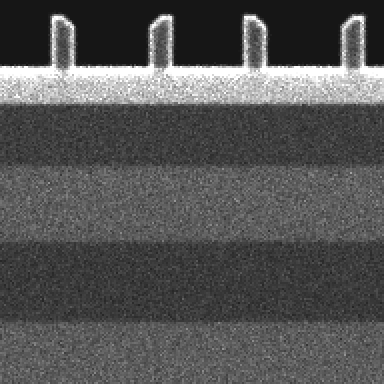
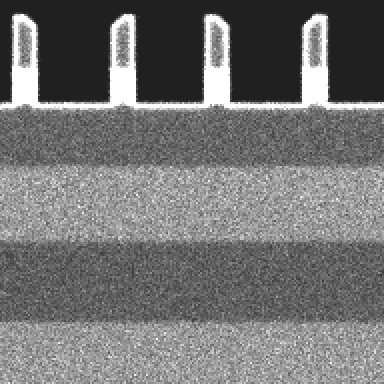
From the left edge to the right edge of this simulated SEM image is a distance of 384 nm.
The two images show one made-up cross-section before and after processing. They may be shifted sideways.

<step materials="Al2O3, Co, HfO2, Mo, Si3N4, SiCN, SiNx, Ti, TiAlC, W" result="removed HfO2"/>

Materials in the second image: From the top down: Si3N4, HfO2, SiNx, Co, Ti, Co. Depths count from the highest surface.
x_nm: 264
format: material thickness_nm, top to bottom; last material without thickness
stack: empty 88, SiNx 62, Co 76, Ti 80, Co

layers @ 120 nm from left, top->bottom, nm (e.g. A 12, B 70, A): empty 2, Si3N4 50, HfO2 36, SiNx 62, Co 76, Ti 80, Co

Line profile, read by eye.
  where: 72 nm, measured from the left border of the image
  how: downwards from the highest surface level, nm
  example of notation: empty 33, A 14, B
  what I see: empty 88, SiNx 62, Co 76, Ti 80, Co